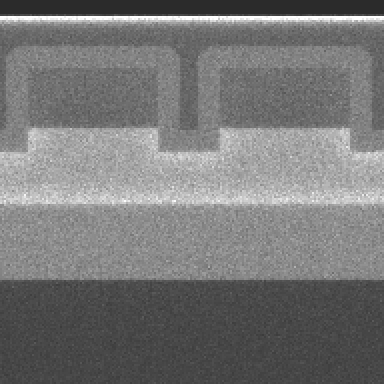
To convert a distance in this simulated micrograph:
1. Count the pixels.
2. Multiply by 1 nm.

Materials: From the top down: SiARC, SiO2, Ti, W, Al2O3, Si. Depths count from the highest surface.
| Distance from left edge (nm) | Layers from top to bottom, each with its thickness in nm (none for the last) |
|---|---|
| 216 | SiARC 30, SiO2 106, W 52, Al2O3 76, Si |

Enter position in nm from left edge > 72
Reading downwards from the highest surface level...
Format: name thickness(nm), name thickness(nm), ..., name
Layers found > SiARC 30, SiO2 22, Ti 60, W 76, Al2O3 76, Si